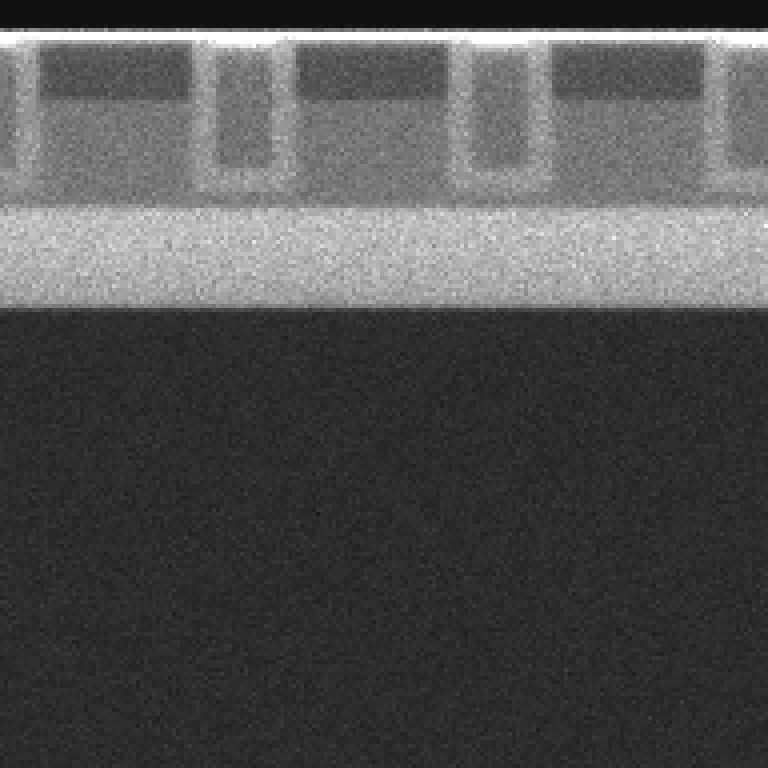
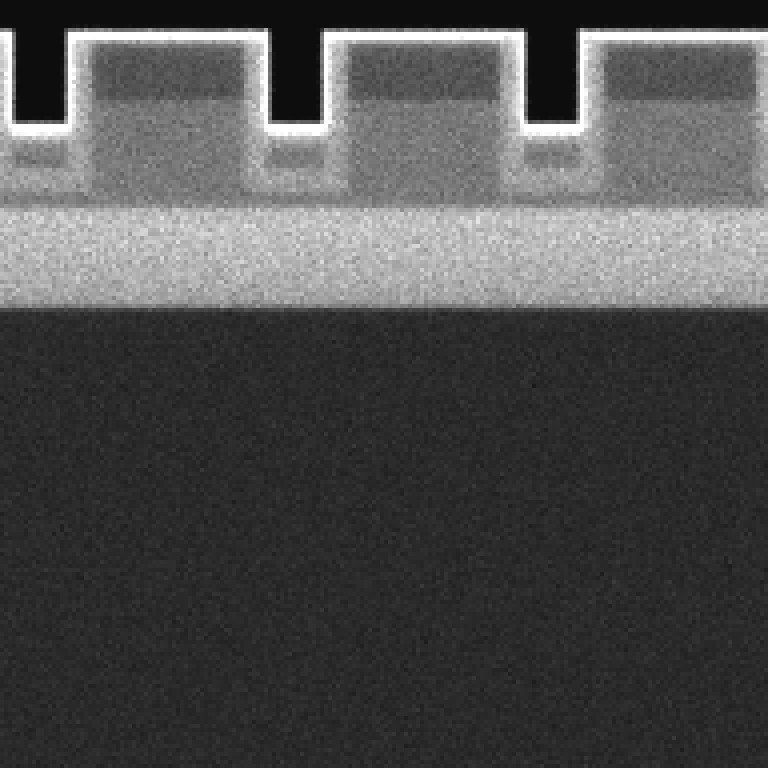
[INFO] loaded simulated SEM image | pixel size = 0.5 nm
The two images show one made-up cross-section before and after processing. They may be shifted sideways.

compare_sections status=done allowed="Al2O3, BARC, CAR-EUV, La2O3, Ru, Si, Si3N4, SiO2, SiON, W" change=removed material="SiO2"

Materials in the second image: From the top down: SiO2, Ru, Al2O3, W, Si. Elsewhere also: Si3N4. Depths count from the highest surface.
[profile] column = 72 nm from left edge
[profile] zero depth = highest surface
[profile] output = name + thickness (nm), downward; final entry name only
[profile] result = Si3N4 34, Al2O3 54, W 50, Si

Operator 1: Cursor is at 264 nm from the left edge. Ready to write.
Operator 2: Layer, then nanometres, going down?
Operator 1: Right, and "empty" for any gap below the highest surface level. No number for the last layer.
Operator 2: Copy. empty 46, SiO2 22, Ru 12, Al2O3 8, W 50, Si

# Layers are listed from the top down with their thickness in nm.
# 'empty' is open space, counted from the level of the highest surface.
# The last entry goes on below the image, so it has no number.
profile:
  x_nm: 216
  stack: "Si3N4 34, Al2O3 54, W 50, Si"